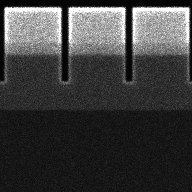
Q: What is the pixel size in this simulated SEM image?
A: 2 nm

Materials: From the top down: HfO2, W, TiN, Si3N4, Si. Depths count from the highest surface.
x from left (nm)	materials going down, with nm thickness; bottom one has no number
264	empty 148, TiN 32, Si3N4 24, Si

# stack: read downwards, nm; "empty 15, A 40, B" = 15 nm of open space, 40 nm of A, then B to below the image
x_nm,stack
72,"HfO2 70, W 24, TiN 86, Si3N4 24, Si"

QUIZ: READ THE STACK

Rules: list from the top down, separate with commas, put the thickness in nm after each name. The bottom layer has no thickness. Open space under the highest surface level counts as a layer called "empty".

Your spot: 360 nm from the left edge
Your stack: HfO2 70, W 24, TiN 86, Si3N4 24, Si